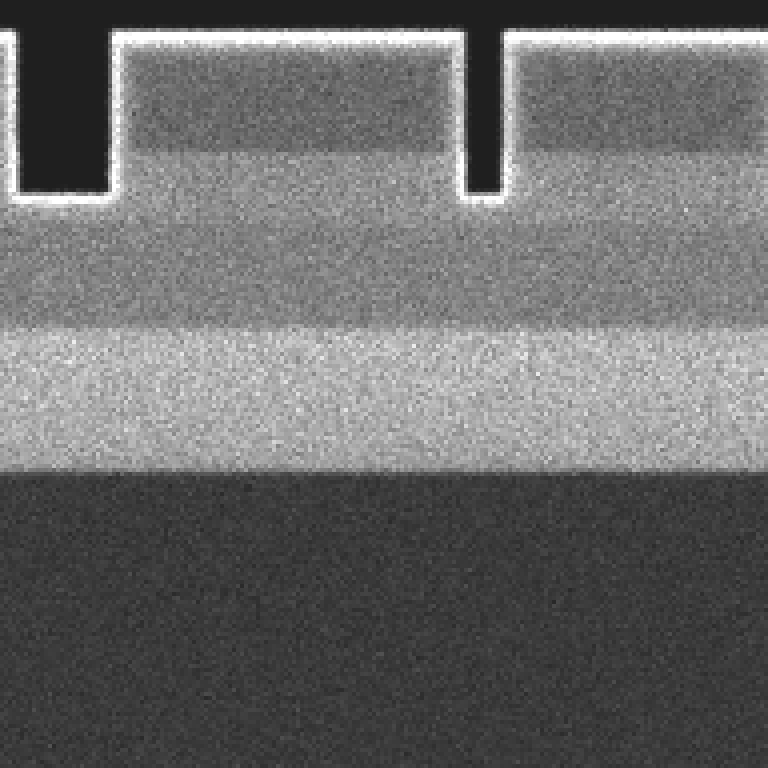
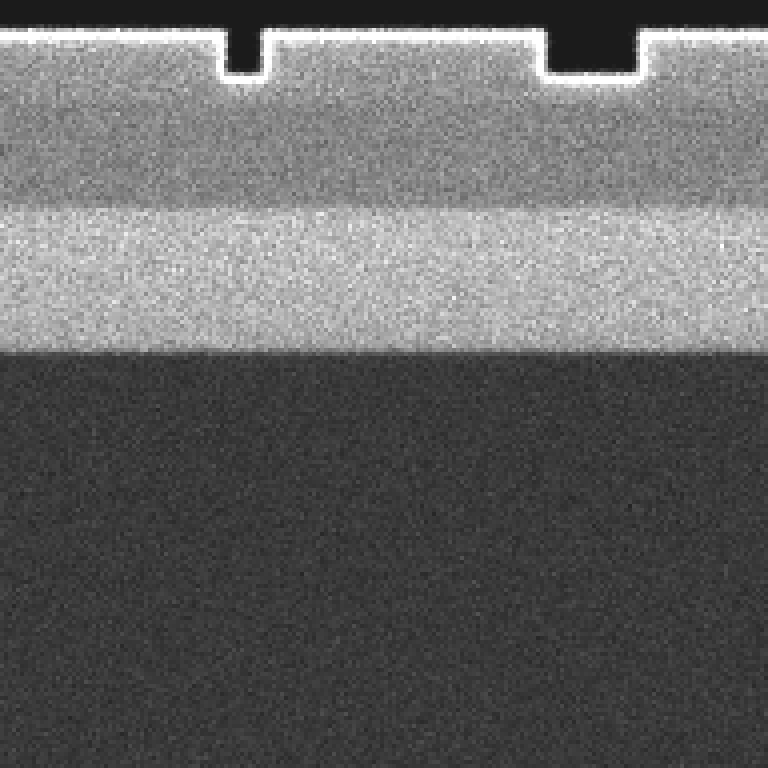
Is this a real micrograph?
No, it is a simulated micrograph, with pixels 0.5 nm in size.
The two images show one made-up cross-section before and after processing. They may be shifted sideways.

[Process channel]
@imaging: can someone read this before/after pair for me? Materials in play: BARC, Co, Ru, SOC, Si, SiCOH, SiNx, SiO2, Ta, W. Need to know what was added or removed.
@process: SOC removed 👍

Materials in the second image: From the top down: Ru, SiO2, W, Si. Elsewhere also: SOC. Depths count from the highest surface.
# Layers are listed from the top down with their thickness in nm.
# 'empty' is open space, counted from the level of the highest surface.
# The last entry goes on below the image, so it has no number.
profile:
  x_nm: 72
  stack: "Ru 36, SiO2 52, W 72, Si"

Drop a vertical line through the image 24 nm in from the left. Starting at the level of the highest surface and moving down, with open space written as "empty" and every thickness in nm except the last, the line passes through Ru 36, SiO2 52, W 72, Si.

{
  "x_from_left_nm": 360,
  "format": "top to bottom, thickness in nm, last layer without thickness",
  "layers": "Ru 36, SiO2 52, W 72, Si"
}